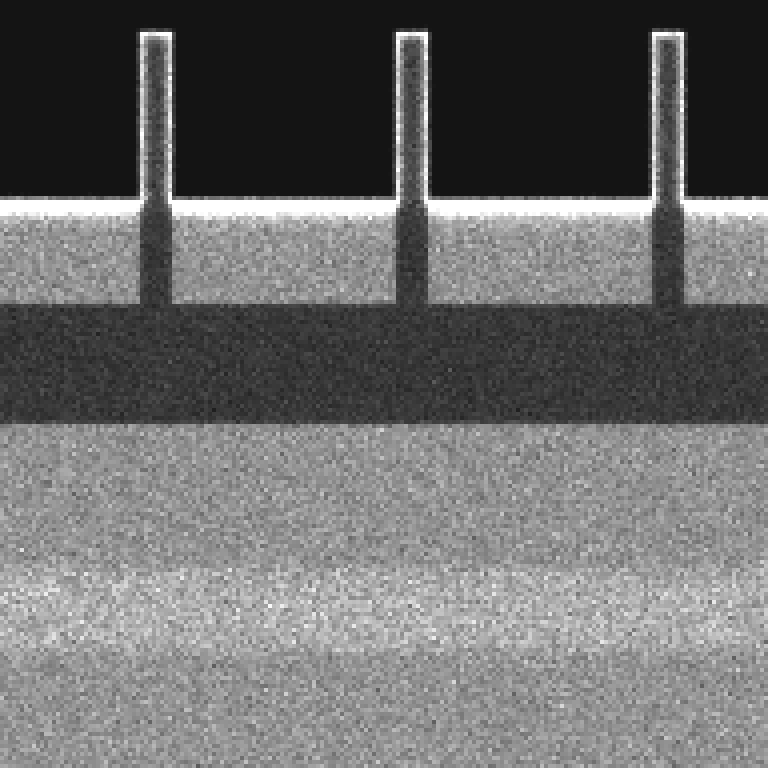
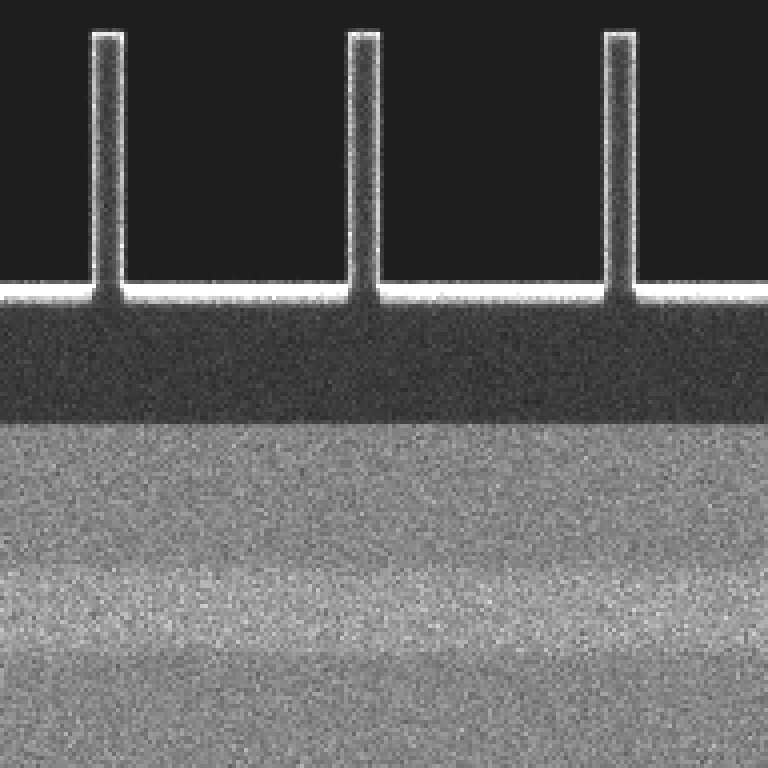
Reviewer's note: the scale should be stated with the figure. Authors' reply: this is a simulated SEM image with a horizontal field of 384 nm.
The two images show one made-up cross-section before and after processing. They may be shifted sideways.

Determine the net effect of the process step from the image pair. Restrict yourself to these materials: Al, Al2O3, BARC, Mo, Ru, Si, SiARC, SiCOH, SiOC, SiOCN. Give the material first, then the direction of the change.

Al2O3: removed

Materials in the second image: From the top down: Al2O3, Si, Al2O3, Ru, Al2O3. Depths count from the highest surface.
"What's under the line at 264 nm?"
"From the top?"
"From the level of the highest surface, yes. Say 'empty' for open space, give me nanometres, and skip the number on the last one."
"empty 126, Al2O3 10, Si 60, Al2O3 72, Ru 42, Al2O3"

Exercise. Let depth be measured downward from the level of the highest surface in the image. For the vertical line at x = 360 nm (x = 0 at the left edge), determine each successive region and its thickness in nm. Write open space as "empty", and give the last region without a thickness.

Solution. empty 126, Al2O3 10, Si 60, Al2O3 72, Ru 42, Al2O3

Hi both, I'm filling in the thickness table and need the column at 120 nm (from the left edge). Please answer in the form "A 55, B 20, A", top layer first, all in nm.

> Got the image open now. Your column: empty 126, Al2O3 10, Si 60, Al2O3 72, Ru 42, Al2O3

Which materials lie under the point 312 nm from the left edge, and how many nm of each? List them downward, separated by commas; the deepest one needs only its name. Si 196, Al2O3 72, Ru 42, Al2O3